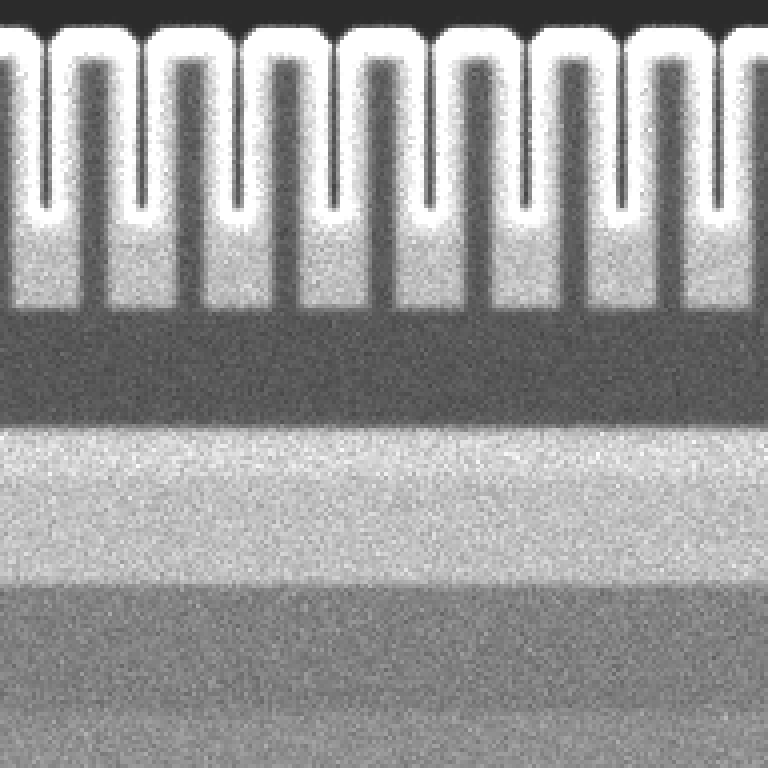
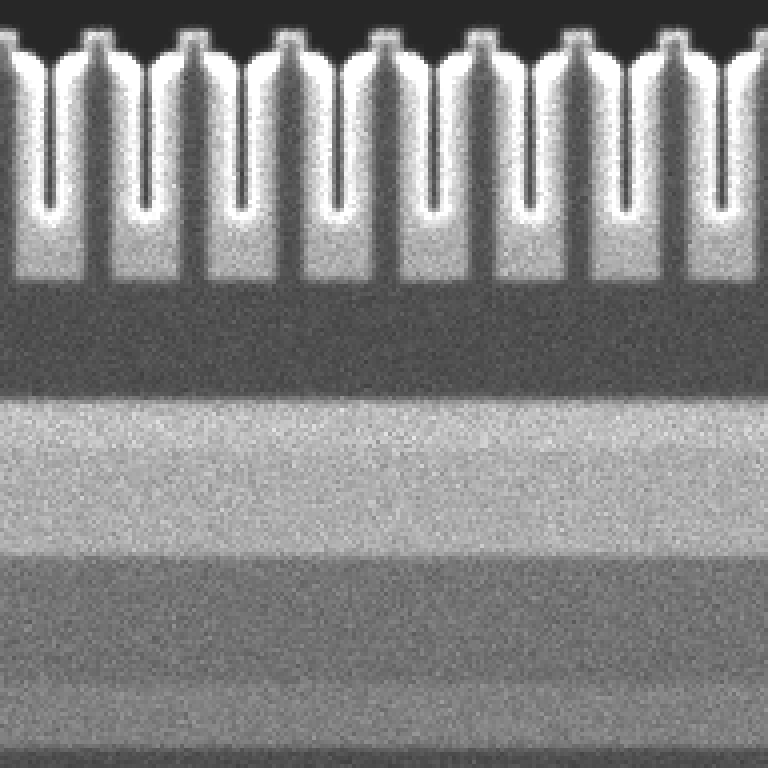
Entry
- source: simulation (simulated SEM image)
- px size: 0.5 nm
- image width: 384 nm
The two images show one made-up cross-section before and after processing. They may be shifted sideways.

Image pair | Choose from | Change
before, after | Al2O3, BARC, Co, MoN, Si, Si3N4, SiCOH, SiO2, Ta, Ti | Al2O3 (removed)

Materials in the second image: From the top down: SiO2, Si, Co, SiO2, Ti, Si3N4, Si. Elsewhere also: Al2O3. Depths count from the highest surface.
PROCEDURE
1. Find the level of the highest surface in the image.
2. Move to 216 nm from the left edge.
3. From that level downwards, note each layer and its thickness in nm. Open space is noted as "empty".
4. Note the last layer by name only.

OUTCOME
empty 90, SiO2 34, Si 60, Co 24, SiO2 54, Ti 64, Si3N4 32, Si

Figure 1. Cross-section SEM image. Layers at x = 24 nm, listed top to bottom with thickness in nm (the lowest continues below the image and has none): empty 90, SiO2 34, Si 60, Co 24, SiO2 54, Ti 64, Si3N4 32, Si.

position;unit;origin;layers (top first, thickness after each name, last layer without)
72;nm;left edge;empty 90, SiO2 34, Si 60, Co 24, SiO2 54, Ti 64, Si3N4 32, Si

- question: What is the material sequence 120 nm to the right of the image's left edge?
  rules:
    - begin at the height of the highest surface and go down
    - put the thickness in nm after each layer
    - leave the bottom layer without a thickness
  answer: empty 90, SiO2 34, Si 60, Co 24, SiO2 54, Ti 64, Si3N4 32, Si